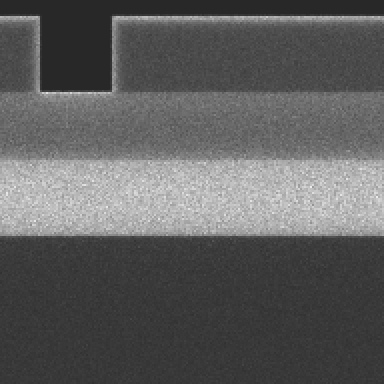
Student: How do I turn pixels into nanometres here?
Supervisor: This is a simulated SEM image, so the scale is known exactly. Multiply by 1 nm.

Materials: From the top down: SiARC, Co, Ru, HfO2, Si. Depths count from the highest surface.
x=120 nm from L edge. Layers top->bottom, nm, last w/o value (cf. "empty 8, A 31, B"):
SiARC 76, Co 60, Ru 8, HfO2 76, Si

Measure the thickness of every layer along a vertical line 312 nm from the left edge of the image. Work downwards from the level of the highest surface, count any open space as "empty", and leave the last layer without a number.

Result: SiARC 76, Co 60, Ru 8, HfO2 76, Si